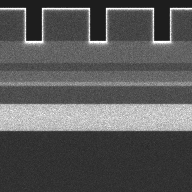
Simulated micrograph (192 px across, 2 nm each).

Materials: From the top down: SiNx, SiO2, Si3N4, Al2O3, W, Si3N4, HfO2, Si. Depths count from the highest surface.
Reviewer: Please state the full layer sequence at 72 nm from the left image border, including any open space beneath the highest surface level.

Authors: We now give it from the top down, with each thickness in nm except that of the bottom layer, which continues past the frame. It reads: empty 66, SiO2 44, Si3N4 16, Al2O3 22, W 8, Si3N4 36, HfO2 54, Si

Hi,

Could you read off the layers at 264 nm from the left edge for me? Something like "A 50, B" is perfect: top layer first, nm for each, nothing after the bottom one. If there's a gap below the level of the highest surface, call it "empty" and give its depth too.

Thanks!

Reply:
SiNx 66, SiO2 44, Si3N4 16, Al2O3 22, W 8, Si3N4 36, HfO2 54, Si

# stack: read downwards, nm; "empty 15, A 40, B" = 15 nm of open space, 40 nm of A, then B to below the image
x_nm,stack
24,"SiNx 66, SiO2 44, Si3N4 16, Al2O3 22, W 8, Si3N4 36, HfO2 54, Si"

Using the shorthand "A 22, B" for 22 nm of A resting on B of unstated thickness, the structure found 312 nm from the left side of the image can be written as empty 66, SiO2 44, Si3N4 16, Al2O3 22, W 8, Si3N4 36, HfO2 54, Si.